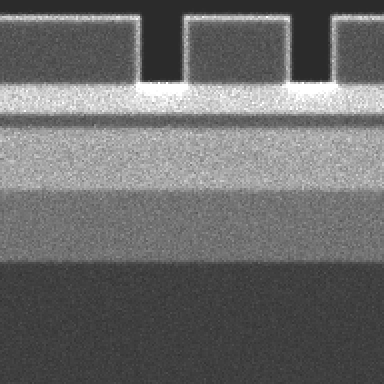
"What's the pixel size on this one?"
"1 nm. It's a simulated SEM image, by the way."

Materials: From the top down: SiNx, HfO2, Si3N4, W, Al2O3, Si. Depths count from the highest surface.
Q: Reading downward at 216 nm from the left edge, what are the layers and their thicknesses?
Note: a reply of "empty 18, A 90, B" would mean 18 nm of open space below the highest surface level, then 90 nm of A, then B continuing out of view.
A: SiNx 68, HfO2 30, Si3N4 14, W 62, Al2O3 72, Si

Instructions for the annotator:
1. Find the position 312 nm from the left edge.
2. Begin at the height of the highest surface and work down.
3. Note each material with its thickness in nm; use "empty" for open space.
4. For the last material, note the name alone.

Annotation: empty 68, HfO2 30, Si3N4 14, W 62, Al2O3 72, Si